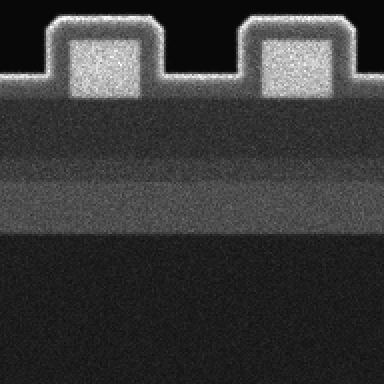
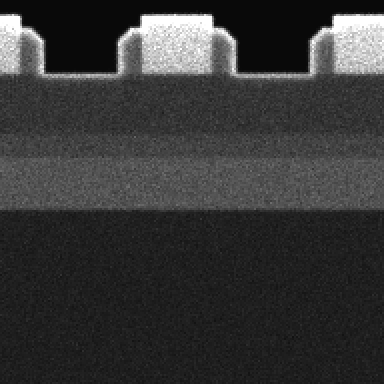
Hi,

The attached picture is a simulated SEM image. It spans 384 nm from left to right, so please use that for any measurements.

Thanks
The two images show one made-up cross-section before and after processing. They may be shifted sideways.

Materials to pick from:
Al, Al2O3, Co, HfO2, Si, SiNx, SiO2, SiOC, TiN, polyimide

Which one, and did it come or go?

SiO2 - removed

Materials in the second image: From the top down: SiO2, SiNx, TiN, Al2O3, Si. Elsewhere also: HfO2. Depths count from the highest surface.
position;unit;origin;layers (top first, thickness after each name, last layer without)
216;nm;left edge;empty 12, SiO2 46, SiNx 60, TiN 24, Al2O3 52, Si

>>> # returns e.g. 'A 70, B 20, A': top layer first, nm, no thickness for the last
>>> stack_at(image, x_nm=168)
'HfO2 58, SiNx 60, TiN 24, Al2O3 52, Si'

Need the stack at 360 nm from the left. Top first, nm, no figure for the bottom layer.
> HfO2 58, SiNx 60, TiN 24, Al2O3 52, Si